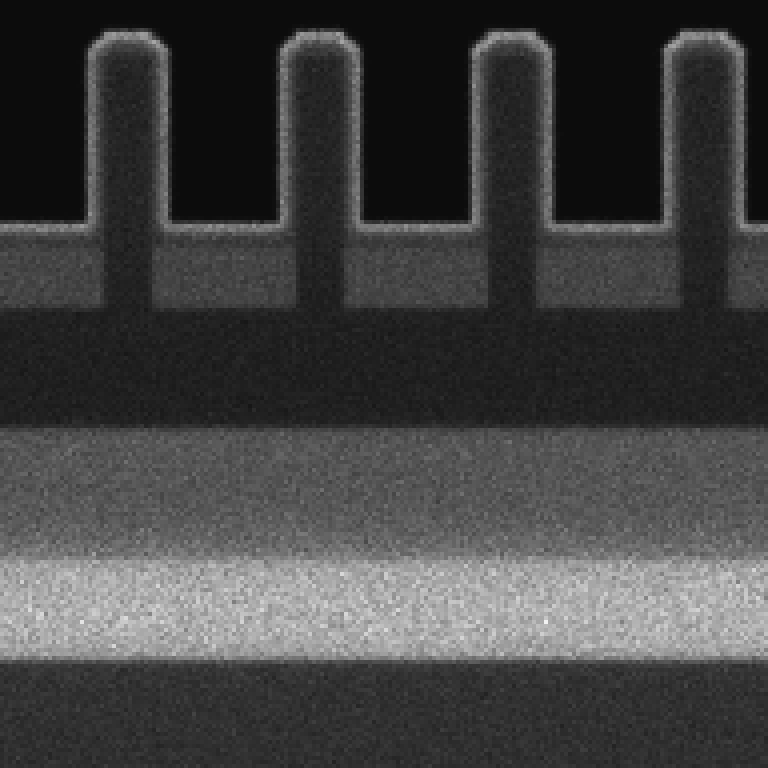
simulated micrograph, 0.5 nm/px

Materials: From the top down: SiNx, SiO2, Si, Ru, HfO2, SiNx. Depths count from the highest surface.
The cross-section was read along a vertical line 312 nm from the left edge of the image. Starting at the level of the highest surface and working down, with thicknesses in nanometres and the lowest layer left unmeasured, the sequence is empty 96, SiNx 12, SiO2 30, Si 60, Ru 66, HfO2 50, SiNx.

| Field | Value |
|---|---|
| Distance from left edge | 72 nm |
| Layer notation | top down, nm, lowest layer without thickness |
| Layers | SiNx 12, Si 186, Ru 66, HfO2 50, SiNx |